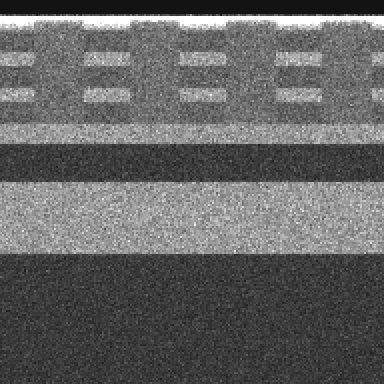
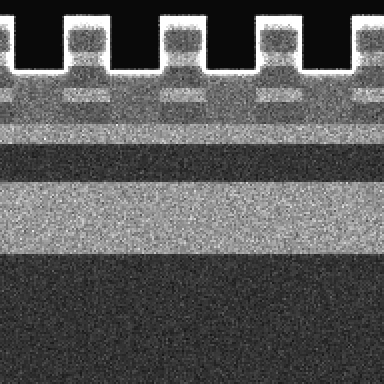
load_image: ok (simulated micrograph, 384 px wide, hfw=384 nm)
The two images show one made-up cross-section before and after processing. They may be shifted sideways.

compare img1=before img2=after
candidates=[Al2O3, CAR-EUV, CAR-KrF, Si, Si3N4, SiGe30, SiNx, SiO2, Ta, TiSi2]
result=removed:Si3N4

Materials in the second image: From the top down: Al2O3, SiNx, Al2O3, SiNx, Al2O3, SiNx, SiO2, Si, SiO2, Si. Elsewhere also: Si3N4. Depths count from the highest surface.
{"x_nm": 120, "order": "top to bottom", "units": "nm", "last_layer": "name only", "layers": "empty 54, Si3N4 54, SiO2 20, Si 38, SiO2 72, Si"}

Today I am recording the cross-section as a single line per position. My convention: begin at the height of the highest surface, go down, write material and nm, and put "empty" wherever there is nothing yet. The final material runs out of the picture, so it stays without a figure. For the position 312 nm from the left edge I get empty 54, Si3N4 54, SiO2 20, Si 38, SiO2 72, Si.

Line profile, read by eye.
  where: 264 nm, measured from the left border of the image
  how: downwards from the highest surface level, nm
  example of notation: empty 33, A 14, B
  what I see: Al2O3 14, SiNx 22, Al2O3 14, SiNx 22, Al2O3 14, SiNx 22, SiO2 20, Si 38, SiO2 72, Si